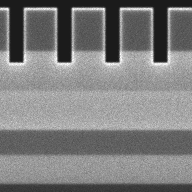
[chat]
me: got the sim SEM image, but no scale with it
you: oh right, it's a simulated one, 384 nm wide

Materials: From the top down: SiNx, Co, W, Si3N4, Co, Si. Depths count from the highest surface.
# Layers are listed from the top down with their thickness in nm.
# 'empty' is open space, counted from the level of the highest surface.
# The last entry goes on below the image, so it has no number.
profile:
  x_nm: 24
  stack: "empty 110, Co 56, W 78, Si3N4 50, Co 58, Si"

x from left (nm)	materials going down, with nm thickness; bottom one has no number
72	SiNx 86, Co 80, W 78, Si3N4 50, Co 58, Si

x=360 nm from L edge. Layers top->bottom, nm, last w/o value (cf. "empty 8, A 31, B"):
SiNx 86, Co 80, W 78, Si3N4 50, Co 58, Si